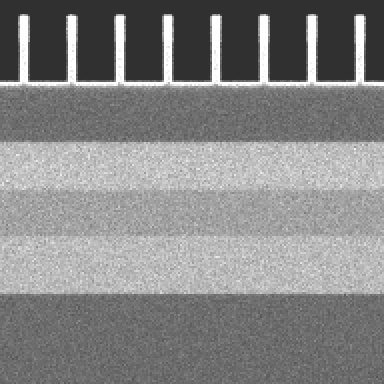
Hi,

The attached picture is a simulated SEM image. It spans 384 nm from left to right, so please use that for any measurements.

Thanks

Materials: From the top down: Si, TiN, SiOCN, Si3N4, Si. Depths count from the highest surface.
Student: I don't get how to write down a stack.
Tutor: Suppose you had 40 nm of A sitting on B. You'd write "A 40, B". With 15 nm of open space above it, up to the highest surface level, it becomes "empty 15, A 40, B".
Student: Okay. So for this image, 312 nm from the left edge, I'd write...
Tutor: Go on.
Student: Si 126, TiN 48, SiOCN 46, Si3N4 58, Si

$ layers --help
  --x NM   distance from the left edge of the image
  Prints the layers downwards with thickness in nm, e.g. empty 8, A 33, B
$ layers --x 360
Si 126, TiN 48, SiOCN 46, Si3N4 58, Si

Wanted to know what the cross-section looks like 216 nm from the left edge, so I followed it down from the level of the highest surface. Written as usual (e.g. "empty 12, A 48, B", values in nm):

Si 126, TiN 48, SiOCN 46, Si3N4 58, Si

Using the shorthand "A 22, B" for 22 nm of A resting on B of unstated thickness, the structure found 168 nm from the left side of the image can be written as Si 126, TiN 48, SiOCN 46, Si3N4 58, Si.